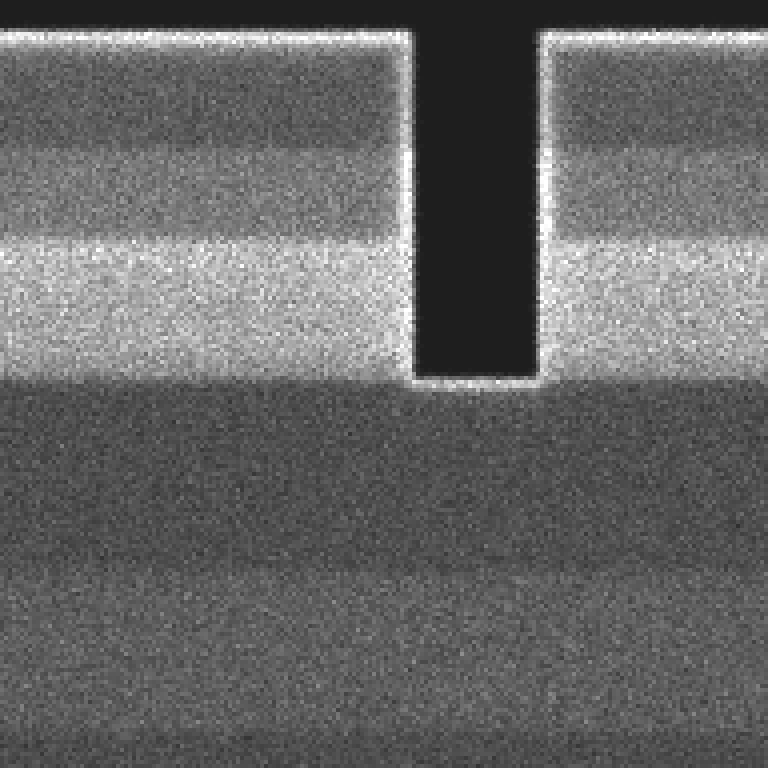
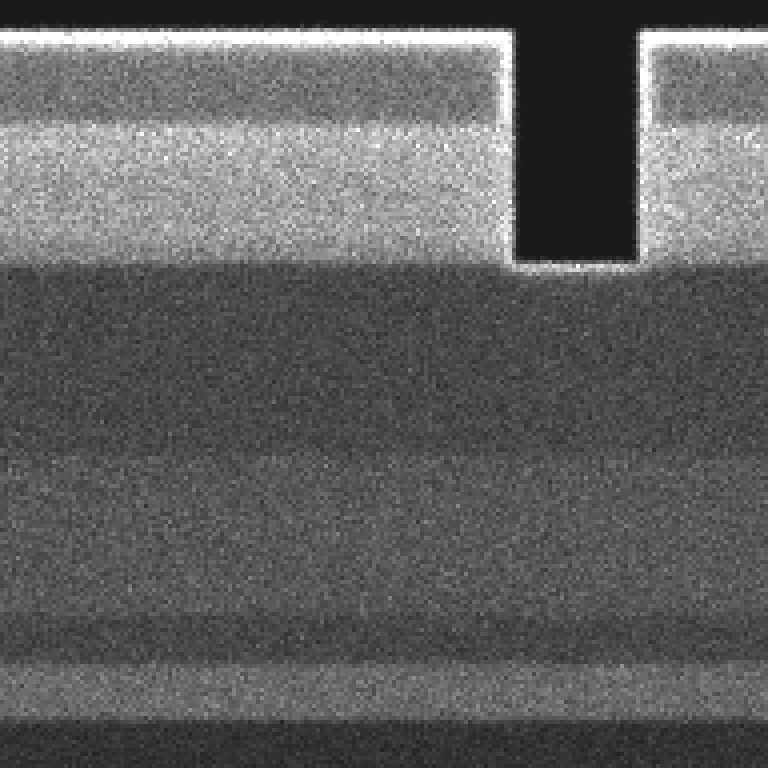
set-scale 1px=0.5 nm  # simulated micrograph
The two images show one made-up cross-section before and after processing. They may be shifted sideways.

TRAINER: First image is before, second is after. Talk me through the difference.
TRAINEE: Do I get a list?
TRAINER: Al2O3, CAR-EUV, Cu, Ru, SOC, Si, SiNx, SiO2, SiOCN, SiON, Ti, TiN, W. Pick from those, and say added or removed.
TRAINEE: removed: SOC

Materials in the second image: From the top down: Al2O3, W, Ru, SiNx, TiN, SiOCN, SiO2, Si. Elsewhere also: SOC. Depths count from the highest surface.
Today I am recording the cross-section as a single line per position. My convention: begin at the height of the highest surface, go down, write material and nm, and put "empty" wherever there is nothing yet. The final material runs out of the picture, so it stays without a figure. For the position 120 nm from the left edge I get Al2O3 46, W 58, Ru 12, SiNx 96, TiN 80, SiOCN 24, SiO2 28, Si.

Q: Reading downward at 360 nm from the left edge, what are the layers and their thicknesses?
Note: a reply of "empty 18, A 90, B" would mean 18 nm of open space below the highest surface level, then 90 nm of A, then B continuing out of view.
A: Al2O3 46, W 58, Ru 12, SiNx 96, TiN 80, SiOCN 24, SiO2 28, Si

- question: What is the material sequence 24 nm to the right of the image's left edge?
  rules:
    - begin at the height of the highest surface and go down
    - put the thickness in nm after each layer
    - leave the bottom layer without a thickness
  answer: Al2O3 46, W 58, Ru 12, SiNx 96, TiN 80, SiOCN 24, SiO2 28, Si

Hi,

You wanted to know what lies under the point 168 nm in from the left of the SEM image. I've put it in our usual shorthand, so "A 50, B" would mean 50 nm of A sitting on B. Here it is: Al2O3 46, W 58, Ru 12, SiNx 96, TiN 80, SiOCN 24, SiO2 28, Si